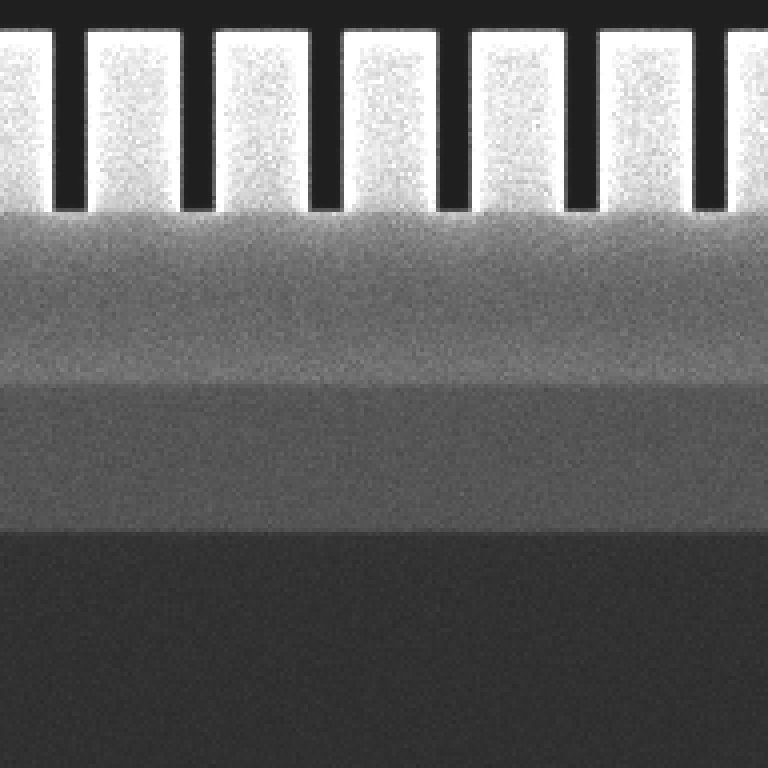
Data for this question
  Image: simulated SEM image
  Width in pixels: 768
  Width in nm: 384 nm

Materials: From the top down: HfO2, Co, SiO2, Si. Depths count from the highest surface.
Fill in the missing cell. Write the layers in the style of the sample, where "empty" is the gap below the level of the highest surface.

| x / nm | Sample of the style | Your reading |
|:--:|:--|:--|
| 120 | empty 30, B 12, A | HfO2 90, Co 86, SiO2 74, Si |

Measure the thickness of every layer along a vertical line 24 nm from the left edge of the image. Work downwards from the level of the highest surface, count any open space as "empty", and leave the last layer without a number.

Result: HfO2 90, Co 86, SiO2 74, Si